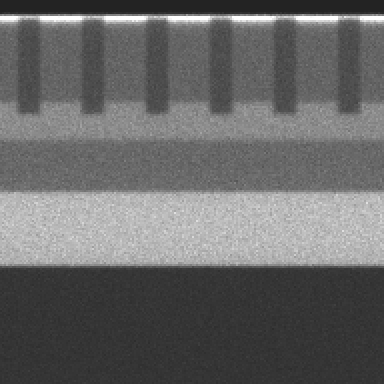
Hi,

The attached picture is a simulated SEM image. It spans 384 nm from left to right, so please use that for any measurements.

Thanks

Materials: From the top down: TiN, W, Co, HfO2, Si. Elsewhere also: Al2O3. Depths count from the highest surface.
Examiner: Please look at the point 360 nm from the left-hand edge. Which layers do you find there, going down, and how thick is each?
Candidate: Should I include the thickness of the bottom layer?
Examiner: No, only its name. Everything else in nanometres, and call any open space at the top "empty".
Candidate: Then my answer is Al2O3 86, W 38, Co 52, HfO2 74, Si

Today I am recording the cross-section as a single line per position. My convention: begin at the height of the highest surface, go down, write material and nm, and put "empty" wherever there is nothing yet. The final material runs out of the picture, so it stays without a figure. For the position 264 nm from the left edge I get Al2O3 86, W 38, Co 52, HfO2 74, Si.